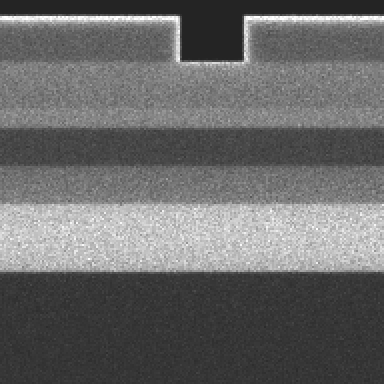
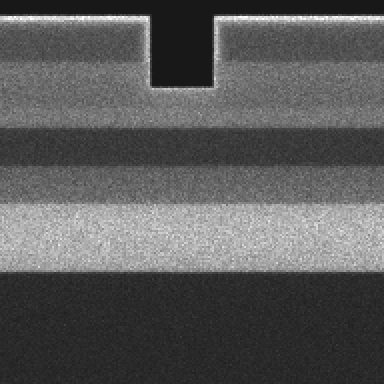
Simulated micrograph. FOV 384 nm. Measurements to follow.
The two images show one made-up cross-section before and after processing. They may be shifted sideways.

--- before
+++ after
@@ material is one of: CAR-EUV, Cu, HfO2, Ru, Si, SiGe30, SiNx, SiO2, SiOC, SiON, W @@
Ru removed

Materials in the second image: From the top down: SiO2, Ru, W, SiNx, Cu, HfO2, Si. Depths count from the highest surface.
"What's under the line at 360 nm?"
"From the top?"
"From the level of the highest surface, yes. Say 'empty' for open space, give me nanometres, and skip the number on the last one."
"SiO2 46, Ru 46, W 20, SiNx 38, Cu 38, HfO2 68, Si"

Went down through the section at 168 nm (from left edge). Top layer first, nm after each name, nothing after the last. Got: empty 72, Ru 20, W 20, SiNx 38, Cu 38, HfO2 68, Si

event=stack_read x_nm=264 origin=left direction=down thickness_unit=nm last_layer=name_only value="SiO2 46, Ru 46, W 20, SiNx 38, Cu 38, HfO2 68, Si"